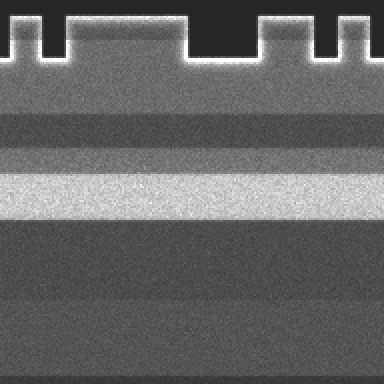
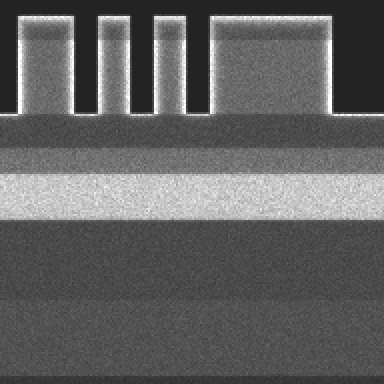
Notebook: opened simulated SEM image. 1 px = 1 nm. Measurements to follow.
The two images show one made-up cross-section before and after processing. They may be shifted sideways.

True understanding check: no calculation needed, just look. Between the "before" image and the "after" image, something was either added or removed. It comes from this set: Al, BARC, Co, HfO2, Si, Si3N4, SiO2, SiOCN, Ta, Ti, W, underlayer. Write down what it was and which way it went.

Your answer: SiO2 (removed)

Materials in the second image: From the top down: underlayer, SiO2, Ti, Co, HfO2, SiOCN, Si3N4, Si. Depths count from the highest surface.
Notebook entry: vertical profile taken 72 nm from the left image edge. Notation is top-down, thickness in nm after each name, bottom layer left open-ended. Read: underlayer 24, SiO2 74, Ti 34, Co 26, HfO2 46, SiOCN 80, Si3N4 76, Si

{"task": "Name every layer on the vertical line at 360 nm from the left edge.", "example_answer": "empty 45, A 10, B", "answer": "empty 98, Ti 34, Co 26, HfO2 46, SiOCN 80, Si3N4 76, Si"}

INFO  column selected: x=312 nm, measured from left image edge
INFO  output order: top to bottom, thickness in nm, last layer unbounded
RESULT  underlayer 24, SiO2 74, Ti 34, Co 26, HfO2 46, SiOCN 80, Si3N4 76, Si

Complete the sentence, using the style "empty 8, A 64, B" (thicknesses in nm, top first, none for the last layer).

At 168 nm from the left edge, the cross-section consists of underlayer 24, SiO2 74, Ti 34, Co 26, HfO2 46, SiOCN 80, Si3N4 76, Si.